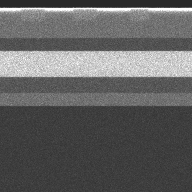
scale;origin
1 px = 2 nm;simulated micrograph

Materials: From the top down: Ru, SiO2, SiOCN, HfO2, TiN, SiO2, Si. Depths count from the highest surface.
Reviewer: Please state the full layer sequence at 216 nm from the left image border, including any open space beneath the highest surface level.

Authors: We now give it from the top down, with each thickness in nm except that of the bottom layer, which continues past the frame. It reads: SiO2 60, SiOCN 26, HfO2 52, TiN 32, SiO2 26, Si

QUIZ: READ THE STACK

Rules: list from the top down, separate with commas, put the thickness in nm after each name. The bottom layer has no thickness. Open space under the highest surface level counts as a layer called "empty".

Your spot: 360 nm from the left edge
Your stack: SiO2 60, SiOCN 26, HfO2 52, TiN 32, SiO2 26, Si